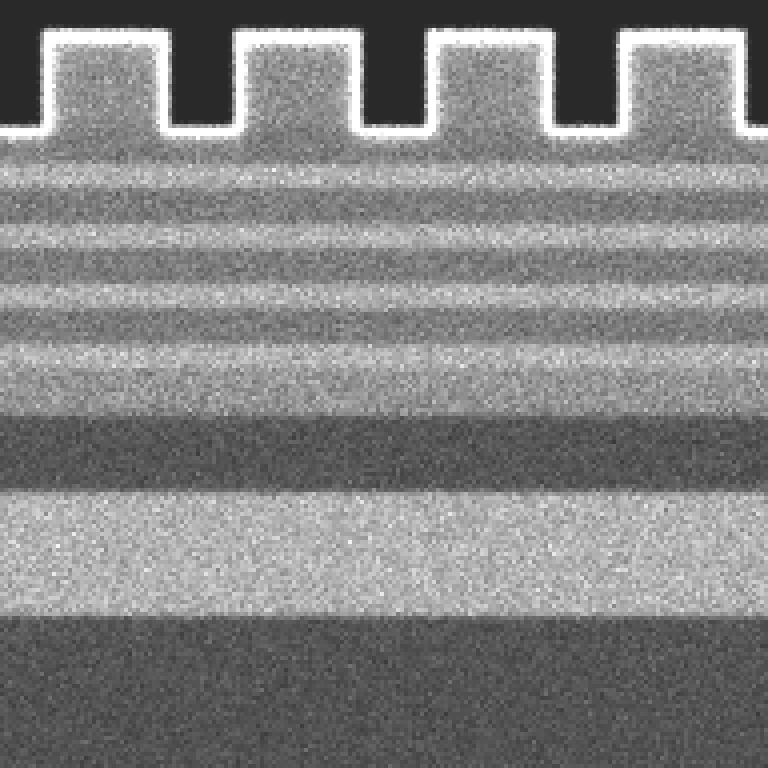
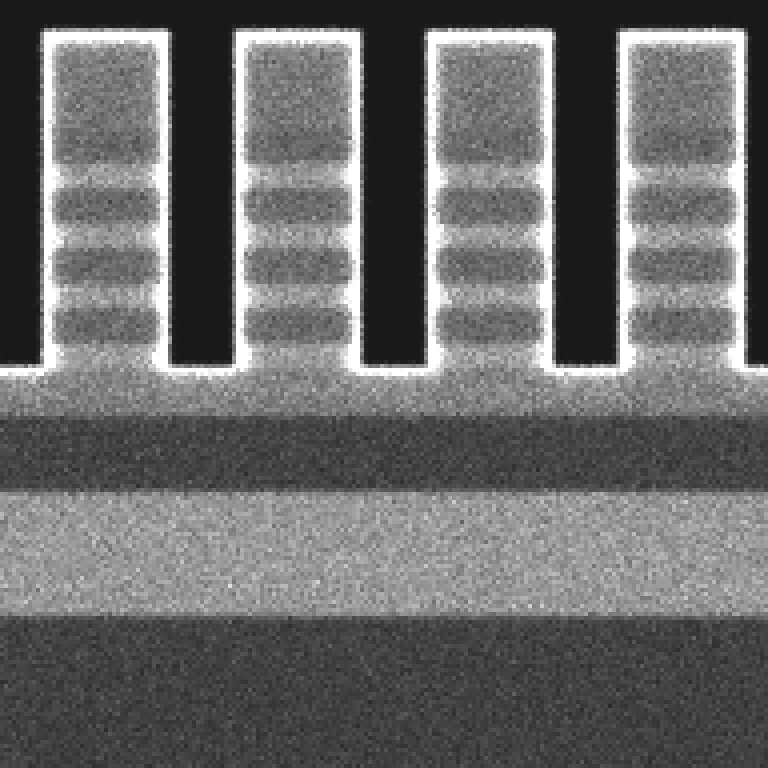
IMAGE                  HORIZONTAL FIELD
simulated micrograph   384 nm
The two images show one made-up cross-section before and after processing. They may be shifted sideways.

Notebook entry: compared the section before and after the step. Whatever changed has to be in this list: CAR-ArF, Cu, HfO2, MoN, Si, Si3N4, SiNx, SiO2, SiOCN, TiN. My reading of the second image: SiNx and SiO2 removed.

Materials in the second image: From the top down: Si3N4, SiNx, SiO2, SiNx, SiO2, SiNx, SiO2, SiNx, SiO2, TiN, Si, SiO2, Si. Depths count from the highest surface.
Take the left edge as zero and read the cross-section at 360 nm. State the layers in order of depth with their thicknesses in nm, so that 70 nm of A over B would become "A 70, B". Si3N4 48, SiNx 18, SiO2 12, SiNx 18, SiO2 12, SiNx 18, SiO2 12, SiNx 18, SiO2 12, TiN 24, Si 38, SiO2 62, Si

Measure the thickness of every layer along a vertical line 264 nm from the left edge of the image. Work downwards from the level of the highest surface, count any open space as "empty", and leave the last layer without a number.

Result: Si3N4 48, SiNx 18, SiO2 12, SiNx 18, SiO2 12, SiNx 18, SiO2 12, SiNx 18, SiO2 12, TiN 24, Si 38, SiO2 62, Si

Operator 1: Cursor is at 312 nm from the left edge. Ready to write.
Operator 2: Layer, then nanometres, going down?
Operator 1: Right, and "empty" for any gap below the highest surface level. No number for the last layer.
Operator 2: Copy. Si3N4 48, SiNx 18, SiO2 12, SiNx 18, SiO2 12, SiNx 18, SiO2 12, SiNx 18, SiO2 12, TiN 24, Si 38, SiO2 62, Si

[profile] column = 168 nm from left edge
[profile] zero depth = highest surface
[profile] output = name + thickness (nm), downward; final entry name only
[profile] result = Si3N4 48, SiNx 18, SiO2 12, SiNx 18, SiO2 12, SiNx 18, SiO2 12, SiNx 18, SiO2 12, TiN 24, Si 38, SiO2 62, Si